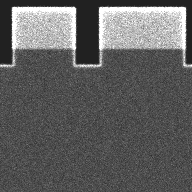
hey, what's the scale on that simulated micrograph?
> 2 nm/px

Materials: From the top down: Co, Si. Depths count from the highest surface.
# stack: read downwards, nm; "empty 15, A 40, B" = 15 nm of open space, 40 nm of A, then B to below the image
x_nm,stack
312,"Co 82, Si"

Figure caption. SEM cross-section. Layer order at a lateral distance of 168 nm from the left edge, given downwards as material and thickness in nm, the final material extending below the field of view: empty 114, Si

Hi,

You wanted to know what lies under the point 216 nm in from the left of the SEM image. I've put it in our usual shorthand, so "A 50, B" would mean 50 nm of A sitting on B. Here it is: Co 82, Si